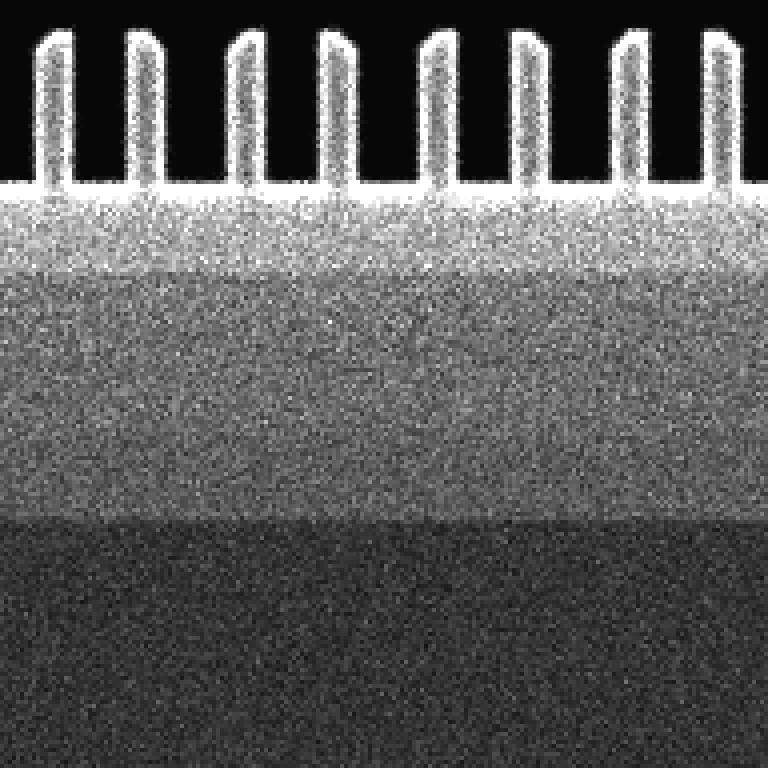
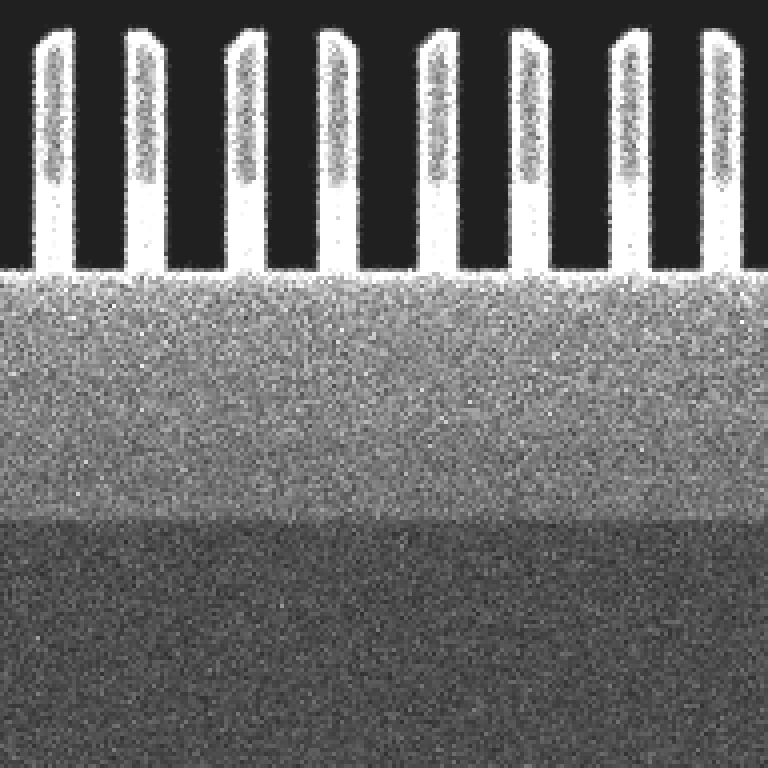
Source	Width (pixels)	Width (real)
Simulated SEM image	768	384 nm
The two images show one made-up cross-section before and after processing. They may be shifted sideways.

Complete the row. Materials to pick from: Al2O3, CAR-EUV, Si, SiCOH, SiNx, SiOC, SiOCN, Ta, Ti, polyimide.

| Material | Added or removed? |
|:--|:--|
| Al2O3 | removed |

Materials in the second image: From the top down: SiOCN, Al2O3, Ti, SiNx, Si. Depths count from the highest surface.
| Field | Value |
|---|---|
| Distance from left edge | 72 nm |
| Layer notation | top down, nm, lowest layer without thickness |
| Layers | SiOCN 76, Al2O3 44, Ti 82, SiNx 42, Si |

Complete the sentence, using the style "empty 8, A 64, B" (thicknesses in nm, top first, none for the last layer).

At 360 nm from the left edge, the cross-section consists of SiOCN 76, Al2O3 44, Ti 82, SiNx 42, Si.